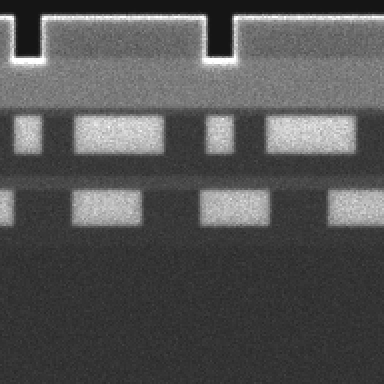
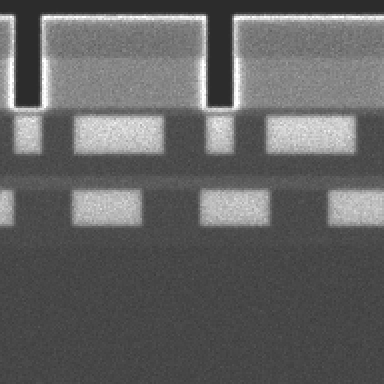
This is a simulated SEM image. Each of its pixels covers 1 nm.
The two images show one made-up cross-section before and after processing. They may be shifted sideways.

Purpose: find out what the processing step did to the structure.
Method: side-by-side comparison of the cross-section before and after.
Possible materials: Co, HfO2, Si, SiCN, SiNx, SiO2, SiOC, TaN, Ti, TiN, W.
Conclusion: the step removed SiO2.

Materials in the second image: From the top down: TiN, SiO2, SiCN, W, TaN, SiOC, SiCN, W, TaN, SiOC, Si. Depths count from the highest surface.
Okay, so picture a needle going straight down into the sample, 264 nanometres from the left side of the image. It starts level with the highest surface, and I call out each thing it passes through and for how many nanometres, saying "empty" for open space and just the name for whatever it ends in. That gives TiN 42, SiO2 50, SiCN 8, SiOC 60, SiCN 14, TaN 36, SiOC 20, Si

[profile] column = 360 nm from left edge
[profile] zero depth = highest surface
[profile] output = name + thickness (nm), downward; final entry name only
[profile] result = TiN 42, SiO2 50, SiCN 8, SiOC 60, SiCN 14, W 30, TaN 6, SiOC 20, Si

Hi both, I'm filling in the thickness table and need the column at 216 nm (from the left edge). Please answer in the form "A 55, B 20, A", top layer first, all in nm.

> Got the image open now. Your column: empty 92, SiCN 8, W 32, TaN 6, SiOC 22, SiCN 14, W 30, TaN 6, SiOC 20, Si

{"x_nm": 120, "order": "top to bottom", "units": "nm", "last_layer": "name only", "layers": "TiN 42, SiO2 50, SiCN 8, W 32, TaN 6, SiOC 22, SiCN 14, W 30, TaN 6, SiOC 20, Si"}